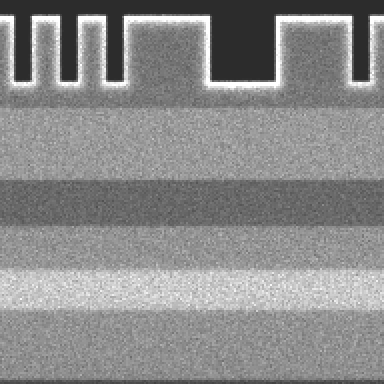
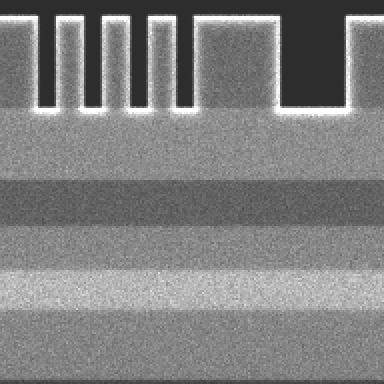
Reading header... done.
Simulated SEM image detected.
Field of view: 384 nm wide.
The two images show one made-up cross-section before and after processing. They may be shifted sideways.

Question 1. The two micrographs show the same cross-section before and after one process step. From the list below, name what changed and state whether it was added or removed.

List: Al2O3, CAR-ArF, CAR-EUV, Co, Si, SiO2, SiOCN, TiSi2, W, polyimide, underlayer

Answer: underlayer, removed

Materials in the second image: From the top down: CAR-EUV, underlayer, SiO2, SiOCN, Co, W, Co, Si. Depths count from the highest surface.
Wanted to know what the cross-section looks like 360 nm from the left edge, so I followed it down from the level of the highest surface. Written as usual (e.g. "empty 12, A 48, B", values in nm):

CAR-EUV 66, underlayer 26, SiO2 72, SiOCN 46, Co 44, W 40, Co 70, Si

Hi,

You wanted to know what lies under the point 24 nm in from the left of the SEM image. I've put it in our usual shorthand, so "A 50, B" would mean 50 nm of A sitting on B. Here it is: CAR-EUV 66, underlayer 26, SiO2 72, SiOCN 46, Co 44, W 40, Co 70, Si